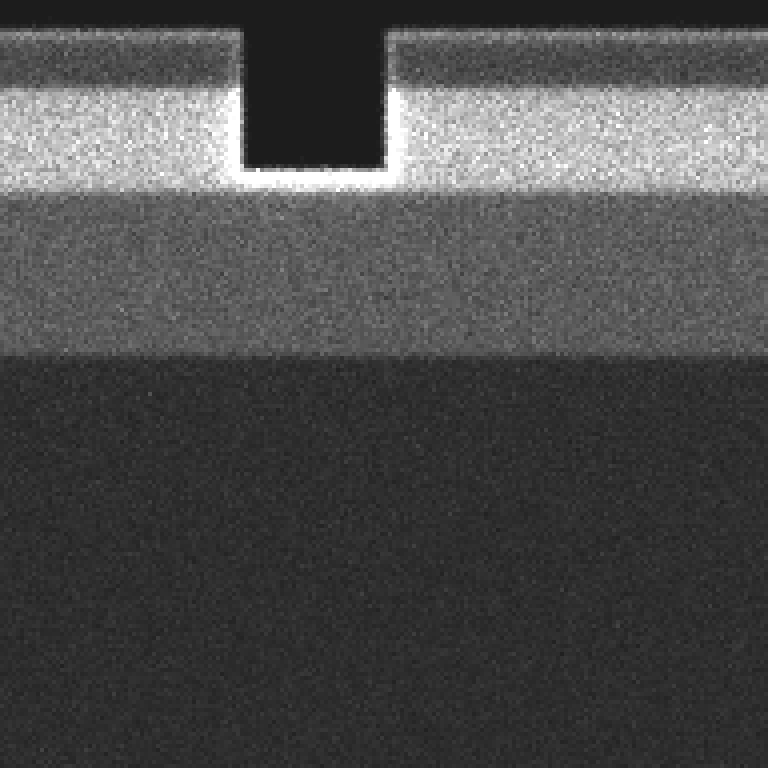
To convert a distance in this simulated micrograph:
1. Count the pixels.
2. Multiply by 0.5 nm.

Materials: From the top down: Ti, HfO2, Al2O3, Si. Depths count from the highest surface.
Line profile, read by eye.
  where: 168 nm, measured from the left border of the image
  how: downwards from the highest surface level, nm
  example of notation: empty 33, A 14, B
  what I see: empty 70, HfO2 10, Al2O3 82, Si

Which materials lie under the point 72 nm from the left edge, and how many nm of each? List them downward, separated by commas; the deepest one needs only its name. Ti 28, HfO2 52, Al2O3 82, Si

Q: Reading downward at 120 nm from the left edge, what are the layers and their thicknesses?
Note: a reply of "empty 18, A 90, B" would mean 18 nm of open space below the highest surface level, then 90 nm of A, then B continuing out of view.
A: empty 70, HfO2 10, Al2O3 82, Si